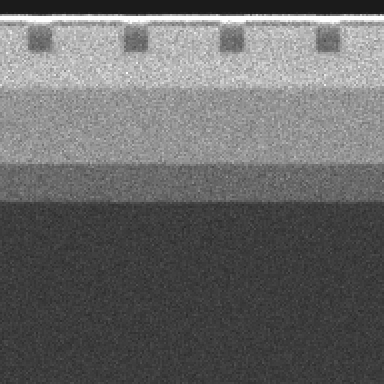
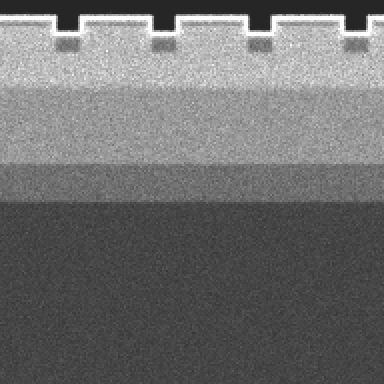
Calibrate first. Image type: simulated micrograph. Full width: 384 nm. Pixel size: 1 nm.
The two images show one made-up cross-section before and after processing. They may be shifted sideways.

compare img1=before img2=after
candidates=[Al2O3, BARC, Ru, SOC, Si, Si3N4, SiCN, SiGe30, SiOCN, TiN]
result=removed:SOC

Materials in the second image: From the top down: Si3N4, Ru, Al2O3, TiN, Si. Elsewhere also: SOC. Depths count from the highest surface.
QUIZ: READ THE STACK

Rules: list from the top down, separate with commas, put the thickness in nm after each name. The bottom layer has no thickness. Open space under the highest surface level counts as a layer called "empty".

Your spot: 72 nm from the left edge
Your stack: empty 16, Si3N4 20, Ru 36, Al2O3 76, TiN 38, Si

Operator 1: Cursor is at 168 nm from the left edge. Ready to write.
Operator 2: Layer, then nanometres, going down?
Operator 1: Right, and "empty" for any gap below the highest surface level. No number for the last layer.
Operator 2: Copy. empty 16, Si3N4 20, Ru 36, Al2O3 76, TiN 38, Si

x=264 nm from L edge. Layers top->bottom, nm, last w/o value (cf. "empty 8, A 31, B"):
empty 16, Si3N4 20, Ru 36, Al2O3 76, TiN 38, Si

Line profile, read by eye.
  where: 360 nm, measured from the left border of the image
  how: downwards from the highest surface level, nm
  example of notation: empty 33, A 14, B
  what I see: empty 16, Si3N4 20, Ru 36, Al2O3 76, TiN 38, Si